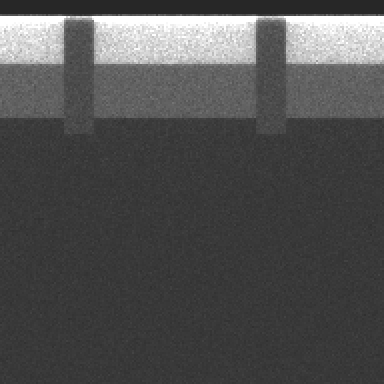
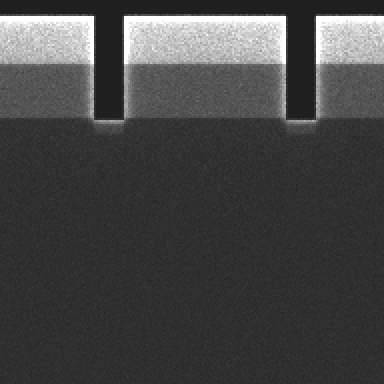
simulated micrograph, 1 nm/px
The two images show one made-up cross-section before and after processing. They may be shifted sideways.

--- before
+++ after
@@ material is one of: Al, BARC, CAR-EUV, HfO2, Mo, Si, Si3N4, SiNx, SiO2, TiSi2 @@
SiNx removed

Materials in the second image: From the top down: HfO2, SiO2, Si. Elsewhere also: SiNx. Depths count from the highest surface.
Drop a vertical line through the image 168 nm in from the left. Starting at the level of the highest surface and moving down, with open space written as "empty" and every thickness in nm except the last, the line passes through HfO2 48, SiO2 54, Si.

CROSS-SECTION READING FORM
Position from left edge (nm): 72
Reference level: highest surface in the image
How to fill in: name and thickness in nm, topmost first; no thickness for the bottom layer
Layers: HfO2 48, SiO2 54, Si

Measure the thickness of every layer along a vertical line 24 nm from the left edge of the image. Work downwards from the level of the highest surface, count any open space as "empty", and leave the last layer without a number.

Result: HfO2 48, SiO2 54, Si